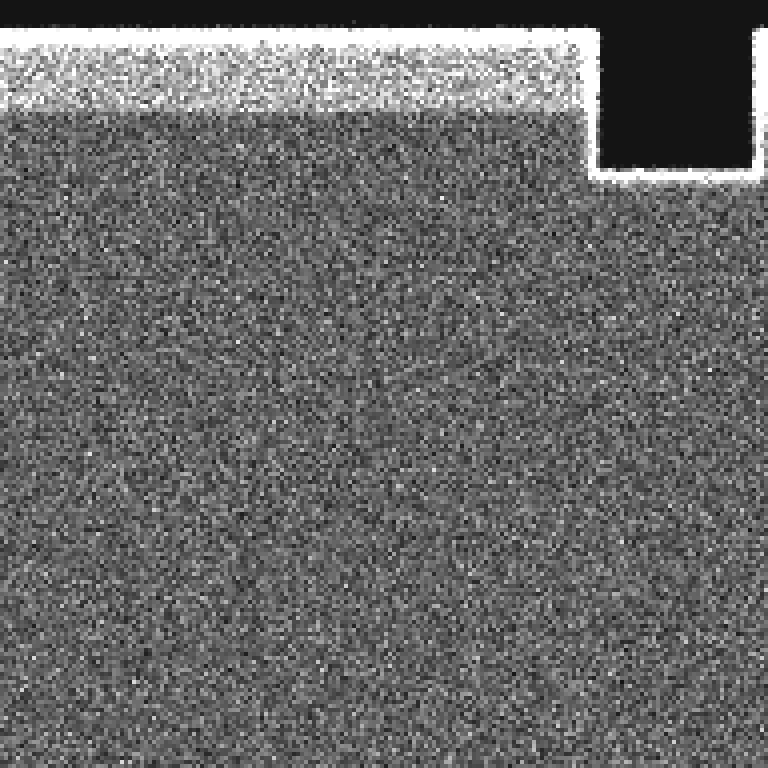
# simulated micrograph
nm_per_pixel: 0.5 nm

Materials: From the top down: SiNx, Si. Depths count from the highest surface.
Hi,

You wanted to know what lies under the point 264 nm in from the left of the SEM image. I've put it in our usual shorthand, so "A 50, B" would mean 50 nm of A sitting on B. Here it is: SiNx 40, Si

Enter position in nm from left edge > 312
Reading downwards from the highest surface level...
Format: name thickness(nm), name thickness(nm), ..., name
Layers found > empty 70, Si